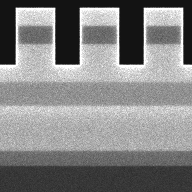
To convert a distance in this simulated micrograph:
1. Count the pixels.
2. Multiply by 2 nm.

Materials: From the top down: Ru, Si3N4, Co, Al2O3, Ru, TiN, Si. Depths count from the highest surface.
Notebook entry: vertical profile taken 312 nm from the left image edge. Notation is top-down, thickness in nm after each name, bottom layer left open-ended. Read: Ru 36, Si3N4 36, Co 76, Al2O3 48, Ru 90, TiN 30, Si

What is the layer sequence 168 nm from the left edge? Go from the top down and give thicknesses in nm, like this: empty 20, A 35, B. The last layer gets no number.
Ru 36, Si3N4 36, Co 76, Al2O3 48, Ru 90, TiN 30, Si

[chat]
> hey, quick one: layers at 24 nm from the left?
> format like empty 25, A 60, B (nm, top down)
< empty 114, Co 34, Al2O3 48, Ru 90, TiN 30, Si